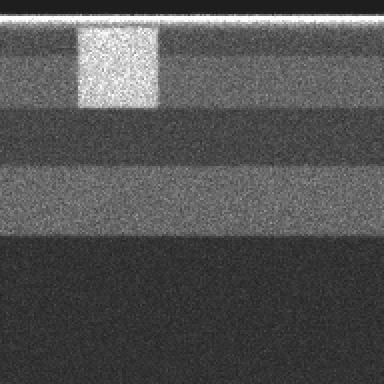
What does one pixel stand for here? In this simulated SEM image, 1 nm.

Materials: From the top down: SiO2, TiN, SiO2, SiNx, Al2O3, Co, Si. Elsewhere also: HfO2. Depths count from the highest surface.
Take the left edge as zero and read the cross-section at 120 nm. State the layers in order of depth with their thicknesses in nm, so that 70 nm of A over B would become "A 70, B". SiO2 12, HfO2 80, SiNx 58, Al2O3 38, Co 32, Si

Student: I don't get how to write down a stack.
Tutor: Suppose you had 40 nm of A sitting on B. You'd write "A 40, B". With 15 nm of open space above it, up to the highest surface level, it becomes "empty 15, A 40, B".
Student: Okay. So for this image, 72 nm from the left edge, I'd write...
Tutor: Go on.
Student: SiO2 12, TiN 28, SiO2 52, SiNx 58, Al2O3 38, Co 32, Si